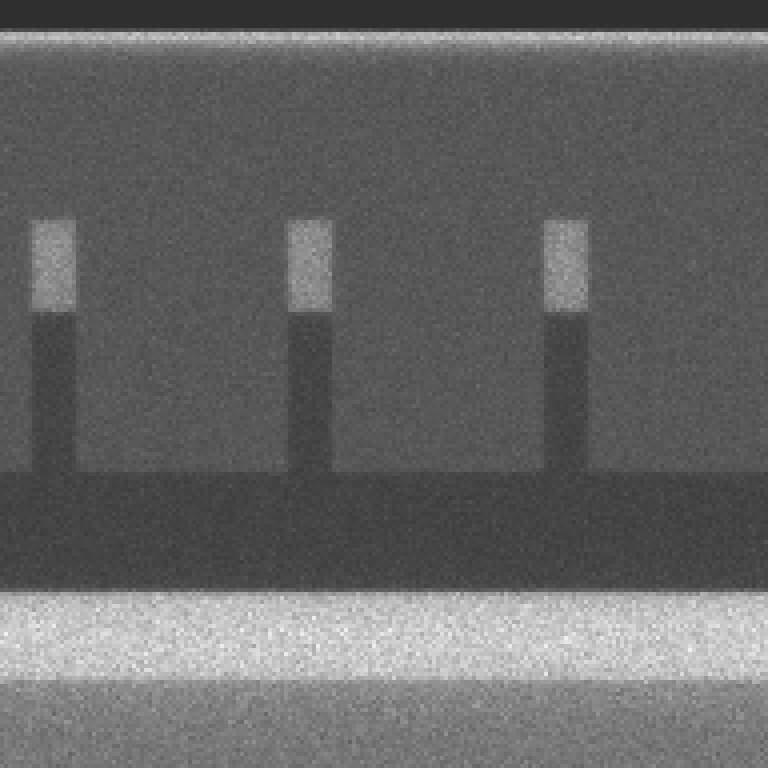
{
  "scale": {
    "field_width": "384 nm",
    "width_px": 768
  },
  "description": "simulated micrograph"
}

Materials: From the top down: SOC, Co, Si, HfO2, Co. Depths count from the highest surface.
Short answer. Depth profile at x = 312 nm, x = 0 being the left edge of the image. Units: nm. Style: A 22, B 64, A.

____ SOC 220, Si 60, HfO2 44, Co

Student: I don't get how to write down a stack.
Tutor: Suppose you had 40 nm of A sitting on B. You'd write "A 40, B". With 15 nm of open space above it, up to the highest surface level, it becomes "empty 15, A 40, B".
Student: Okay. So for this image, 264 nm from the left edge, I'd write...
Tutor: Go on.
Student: SOC 220, Si 60, HfO2 44, Co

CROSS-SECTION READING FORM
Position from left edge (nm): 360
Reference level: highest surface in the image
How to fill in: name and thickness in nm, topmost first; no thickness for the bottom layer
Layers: SOC 220, Si 60, HfO2 44, Co